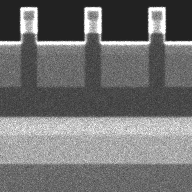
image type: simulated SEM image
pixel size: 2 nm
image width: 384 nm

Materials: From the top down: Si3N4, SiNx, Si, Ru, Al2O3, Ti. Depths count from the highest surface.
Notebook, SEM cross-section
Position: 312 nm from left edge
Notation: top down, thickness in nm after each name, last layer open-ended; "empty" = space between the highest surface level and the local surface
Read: Si3N4 24, Al2O3 26, Si 168, Ru 36, Al2O3 58, Ti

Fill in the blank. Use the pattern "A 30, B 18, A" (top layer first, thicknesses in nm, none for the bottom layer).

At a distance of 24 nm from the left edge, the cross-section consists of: empty 68, Si3N4 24, SiNx 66, Si 60, Ru 36, Al2O3 58, Ti